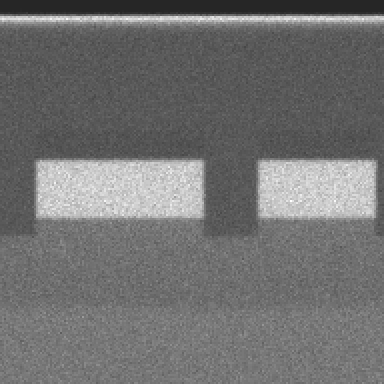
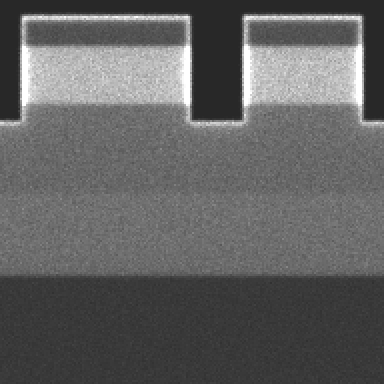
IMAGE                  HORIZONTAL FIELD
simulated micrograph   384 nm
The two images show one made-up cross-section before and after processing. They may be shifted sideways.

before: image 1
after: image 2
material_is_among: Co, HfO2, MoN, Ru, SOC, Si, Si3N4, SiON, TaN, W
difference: SOC, removed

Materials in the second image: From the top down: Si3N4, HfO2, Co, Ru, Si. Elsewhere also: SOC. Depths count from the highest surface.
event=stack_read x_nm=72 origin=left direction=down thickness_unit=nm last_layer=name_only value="Si3N4 30, HfO2 58, Co 90, Ru 82, Si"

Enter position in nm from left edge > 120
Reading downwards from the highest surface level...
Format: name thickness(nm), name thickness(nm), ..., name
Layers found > Si3N4 30, HfO2 58, Co 90, Ru 82, Si